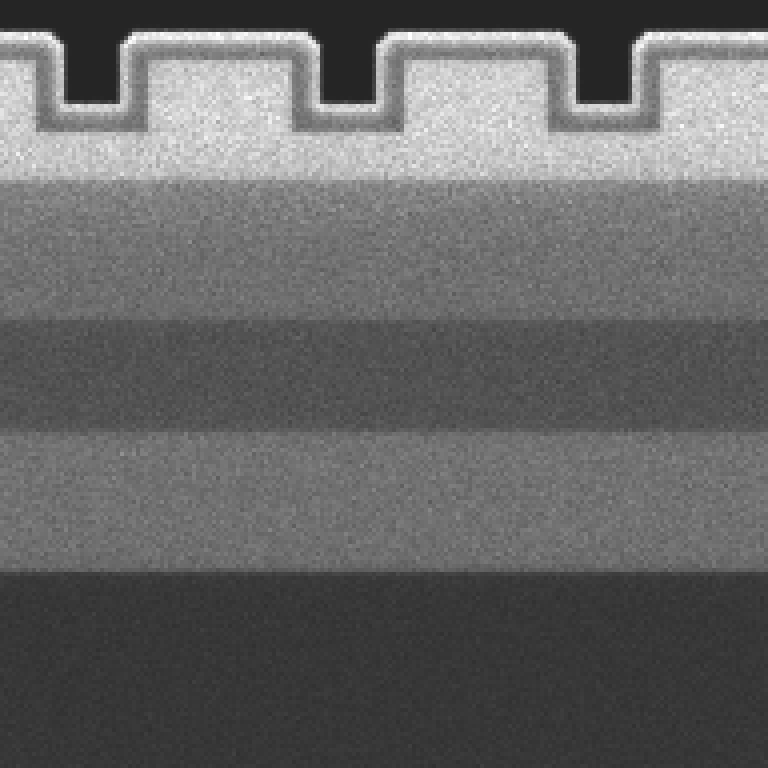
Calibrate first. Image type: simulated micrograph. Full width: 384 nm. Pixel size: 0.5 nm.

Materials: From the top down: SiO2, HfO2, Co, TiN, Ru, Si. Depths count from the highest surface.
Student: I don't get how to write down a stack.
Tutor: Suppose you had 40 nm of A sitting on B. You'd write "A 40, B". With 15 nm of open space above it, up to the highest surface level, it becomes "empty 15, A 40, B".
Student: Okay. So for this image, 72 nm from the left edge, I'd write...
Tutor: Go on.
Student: SiO2 50, HfO2 24, Co 70, TiN 56, Ru 70, Si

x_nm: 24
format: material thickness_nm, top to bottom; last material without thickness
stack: SiO2 50, HfO2 24, Co 70, TiN 56, Ru 70, Si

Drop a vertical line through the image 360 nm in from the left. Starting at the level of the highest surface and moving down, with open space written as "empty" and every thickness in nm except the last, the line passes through SiO2 14, HfO2 60, Co 70, TiN 56, Ru 70, Si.